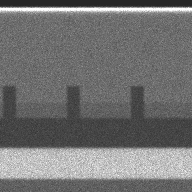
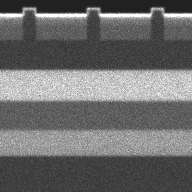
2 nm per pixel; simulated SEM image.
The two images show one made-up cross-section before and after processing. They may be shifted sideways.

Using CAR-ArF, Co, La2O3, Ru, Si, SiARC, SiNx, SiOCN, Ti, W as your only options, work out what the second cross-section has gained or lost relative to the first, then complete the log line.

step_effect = removed SiARC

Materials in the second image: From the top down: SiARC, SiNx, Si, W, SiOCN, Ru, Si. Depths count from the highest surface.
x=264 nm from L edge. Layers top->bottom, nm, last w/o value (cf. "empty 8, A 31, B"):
empty 12, SiARC 22, SiNx 30, Si 60, W 62, SiOCN 58, Ru 52, Si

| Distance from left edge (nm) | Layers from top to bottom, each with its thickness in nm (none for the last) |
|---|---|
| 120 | empty 12, SiARC 22, SiNx 30, Si 60, W 62, SiOCN 58, Ru 52, Si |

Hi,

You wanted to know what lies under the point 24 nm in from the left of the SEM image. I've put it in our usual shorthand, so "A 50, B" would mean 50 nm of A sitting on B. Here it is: empty 12, SiARC 22, SiNx 30, Si 60, W 62, SiOCN 58, Ru 52, Si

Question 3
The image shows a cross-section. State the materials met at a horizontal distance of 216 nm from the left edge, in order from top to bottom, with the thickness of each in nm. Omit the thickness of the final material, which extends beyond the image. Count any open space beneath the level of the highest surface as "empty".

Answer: empty 12, SiARC 22, SiNx 30, Si 60, W 62, SiOCN 58, Ru 52, Si